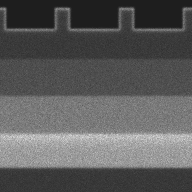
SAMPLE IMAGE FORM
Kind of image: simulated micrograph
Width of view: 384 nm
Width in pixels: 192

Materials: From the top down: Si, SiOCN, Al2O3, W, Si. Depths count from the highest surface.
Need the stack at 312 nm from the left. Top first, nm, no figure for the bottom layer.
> empty 42, Si 60, SiOCN 74, Al2O3 76, W 68, Si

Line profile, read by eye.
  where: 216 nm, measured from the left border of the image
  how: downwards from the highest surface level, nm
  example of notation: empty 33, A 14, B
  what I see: empty 42, Si 60, SiOCN 74, Al2O3 76, W 68, Si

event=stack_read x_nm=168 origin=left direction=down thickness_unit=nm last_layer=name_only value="empty 42, Si 60, SiOCN 74, Al2O3 76, W 68, Si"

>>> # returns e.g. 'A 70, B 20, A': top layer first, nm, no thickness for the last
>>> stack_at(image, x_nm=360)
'empty 42, Si 60, SiOCN 74, Al2O3 76, W 68, Si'